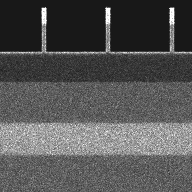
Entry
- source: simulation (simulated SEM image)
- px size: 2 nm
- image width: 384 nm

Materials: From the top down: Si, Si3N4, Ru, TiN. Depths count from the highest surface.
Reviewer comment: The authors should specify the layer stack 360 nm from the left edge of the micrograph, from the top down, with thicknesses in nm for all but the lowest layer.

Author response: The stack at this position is empty 88, Si 60, Si3N4 82, Ru 64, TiN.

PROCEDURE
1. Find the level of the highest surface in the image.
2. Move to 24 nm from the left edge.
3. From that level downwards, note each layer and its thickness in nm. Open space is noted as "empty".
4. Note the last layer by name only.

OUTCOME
empty 88, Si 60, Si3N4 82, Ru 64, TiN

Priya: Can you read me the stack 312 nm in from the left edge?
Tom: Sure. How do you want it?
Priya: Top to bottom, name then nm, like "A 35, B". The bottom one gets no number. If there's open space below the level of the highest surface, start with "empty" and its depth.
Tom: empty 88, Si 60, Si3N4 82, Ru 64, TiN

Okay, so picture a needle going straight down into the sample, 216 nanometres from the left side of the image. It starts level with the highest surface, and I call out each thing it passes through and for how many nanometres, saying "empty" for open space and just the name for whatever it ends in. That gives Si 148, Si3N4 82, Ru 64, TiN